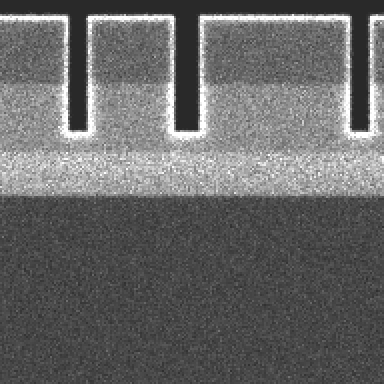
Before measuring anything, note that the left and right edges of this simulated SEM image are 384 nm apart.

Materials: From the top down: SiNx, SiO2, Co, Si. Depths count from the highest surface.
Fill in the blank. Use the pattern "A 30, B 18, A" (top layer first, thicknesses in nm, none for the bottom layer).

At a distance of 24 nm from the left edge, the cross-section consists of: SiNx 68, SiO2 68, Co 44, Si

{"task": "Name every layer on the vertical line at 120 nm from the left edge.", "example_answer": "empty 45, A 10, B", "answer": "SiNx 68, SiO2 68, Co 44, Si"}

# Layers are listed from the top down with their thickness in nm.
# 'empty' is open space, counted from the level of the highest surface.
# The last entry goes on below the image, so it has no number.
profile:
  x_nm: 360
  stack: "empty 116, SiO2 20, Co 44, Si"